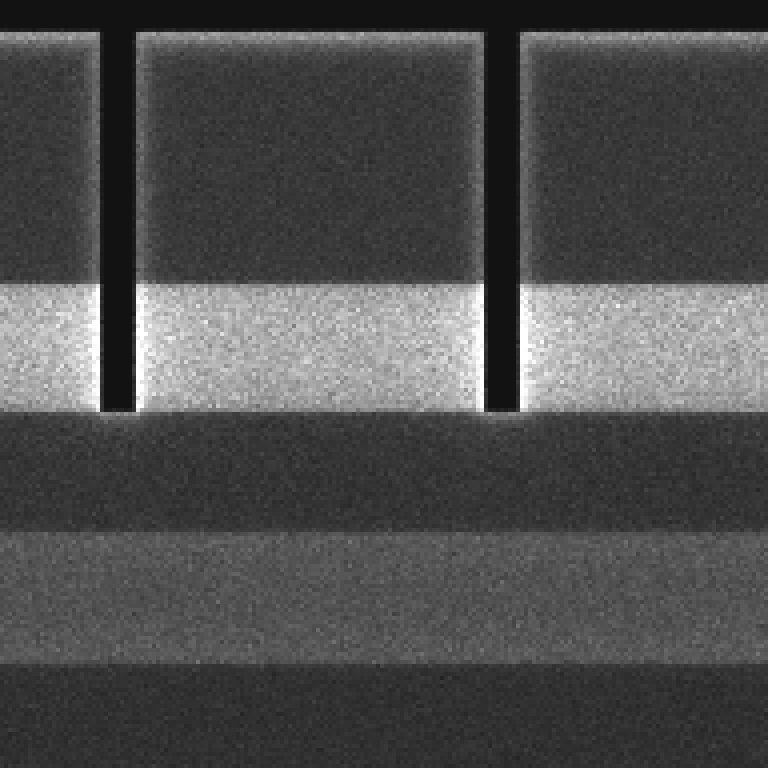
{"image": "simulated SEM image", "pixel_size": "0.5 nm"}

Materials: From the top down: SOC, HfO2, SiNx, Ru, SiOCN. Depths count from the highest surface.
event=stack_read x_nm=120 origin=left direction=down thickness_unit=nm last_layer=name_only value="SOC 126, HfO2 64, SiNx 60, Ru 66, SiOCN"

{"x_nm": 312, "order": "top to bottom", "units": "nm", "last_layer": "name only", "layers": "SOC 126, HfO2 64, SiNx 60, Ru 66, SiOCN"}